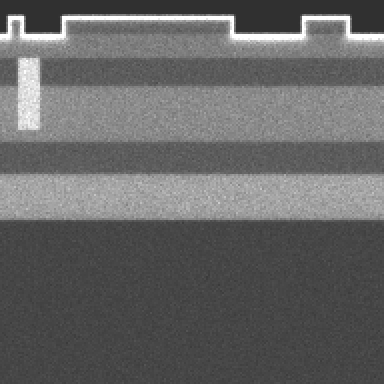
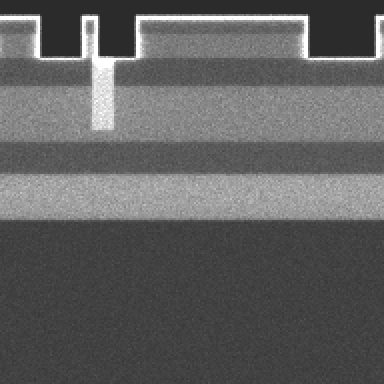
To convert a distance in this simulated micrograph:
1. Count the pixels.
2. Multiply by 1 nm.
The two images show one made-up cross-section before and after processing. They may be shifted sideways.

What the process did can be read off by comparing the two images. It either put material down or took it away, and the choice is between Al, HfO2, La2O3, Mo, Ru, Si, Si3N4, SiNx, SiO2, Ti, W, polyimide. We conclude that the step removed SiO2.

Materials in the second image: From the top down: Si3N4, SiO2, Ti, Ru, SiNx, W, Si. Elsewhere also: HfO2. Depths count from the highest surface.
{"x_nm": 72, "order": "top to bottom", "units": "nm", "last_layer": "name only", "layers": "empty 42, Ti 28, Ru 56, SiNx 32, W 46, Si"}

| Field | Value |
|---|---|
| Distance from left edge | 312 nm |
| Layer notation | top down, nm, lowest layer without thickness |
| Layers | empty 42, Ti 28, Ru 56, SiNx 32, W 46, Si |